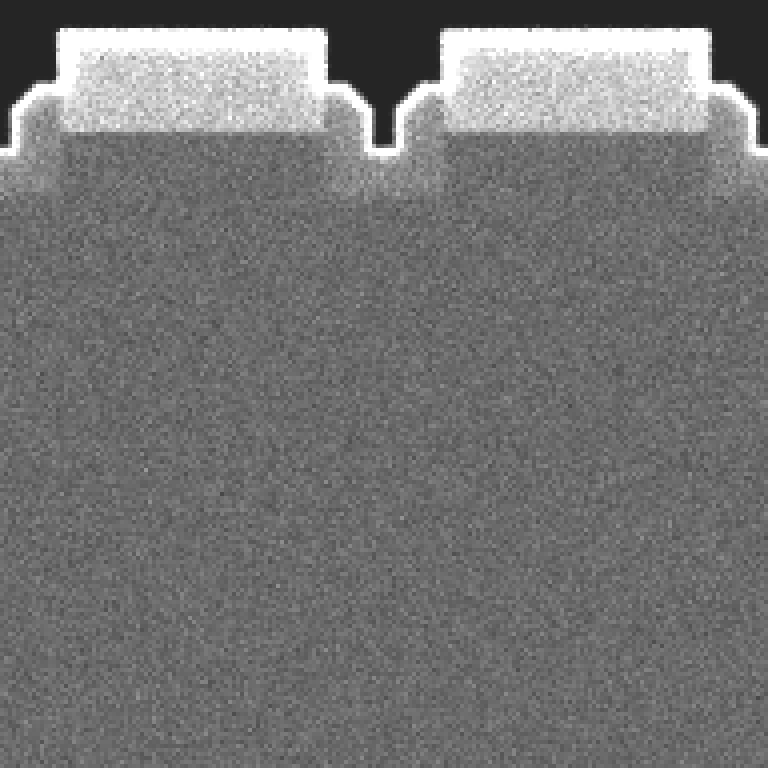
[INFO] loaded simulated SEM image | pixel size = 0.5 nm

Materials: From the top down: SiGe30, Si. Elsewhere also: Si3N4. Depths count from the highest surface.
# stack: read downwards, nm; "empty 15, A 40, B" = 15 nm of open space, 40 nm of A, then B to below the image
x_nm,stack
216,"empty 26, SiGe30 56, Si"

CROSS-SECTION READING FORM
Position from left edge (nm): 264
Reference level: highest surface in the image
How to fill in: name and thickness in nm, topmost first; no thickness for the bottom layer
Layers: Si3N4 50, Si